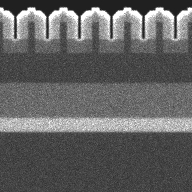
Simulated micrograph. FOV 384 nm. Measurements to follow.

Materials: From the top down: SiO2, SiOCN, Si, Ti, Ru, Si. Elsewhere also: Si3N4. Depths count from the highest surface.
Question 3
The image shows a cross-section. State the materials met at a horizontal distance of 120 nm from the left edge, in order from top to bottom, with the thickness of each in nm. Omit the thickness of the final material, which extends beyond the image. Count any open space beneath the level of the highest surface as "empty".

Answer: Si3N4 28, Si 122, Ti 70, Ru 28, Si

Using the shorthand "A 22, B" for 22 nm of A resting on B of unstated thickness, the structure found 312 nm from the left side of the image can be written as Si3N4 28, Si 122, Ti 70, Ru 28, Si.